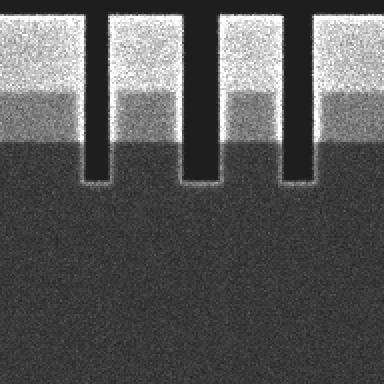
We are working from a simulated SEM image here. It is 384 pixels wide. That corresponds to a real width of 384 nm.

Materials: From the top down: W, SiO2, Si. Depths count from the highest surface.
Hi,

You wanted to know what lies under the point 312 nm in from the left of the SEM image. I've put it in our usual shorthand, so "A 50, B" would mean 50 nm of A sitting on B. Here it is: empty 166, Si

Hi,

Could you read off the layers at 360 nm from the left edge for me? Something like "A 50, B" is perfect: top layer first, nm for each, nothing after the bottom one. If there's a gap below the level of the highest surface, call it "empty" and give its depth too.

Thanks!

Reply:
W 76, SiO2 50, Si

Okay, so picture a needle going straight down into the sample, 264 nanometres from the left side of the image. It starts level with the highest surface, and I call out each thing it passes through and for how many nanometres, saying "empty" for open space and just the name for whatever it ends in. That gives W 76, SiO2 50, Si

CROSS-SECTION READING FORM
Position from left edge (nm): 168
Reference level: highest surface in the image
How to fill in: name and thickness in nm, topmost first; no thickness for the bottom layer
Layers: W 76, SiO2 50, Si